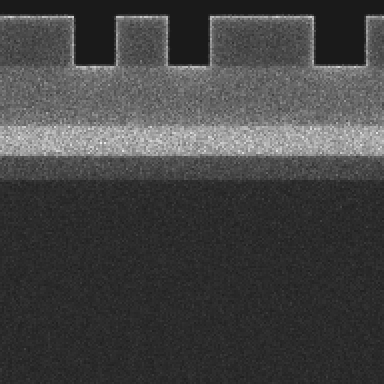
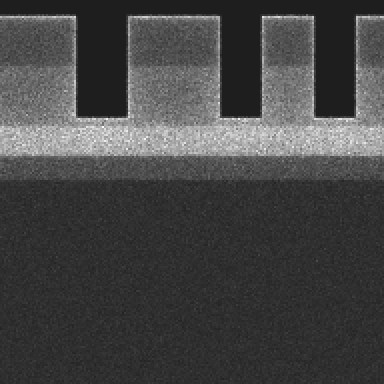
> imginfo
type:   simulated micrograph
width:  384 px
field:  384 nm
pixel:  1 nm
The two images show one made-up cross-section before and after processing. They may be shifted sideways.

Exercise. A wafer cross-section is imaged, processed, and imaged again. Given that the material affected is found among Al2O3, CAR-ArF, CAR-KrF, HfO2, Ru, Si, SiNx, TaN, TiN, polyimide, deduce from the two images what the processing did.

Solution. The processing removed Ru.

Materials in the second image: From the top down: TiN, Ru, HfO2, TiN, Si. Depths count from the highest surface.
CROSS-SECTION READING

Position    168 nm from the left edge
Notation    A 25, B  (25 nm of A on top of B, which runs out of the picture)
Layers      TiN 50, Ru 60, HfO2 30, TiN 24, Si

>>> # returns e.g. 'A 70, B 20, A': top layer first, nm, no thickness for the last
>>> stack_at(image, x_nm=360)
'TiN 50, Ru 60, HfO2 30, TiN 24, Si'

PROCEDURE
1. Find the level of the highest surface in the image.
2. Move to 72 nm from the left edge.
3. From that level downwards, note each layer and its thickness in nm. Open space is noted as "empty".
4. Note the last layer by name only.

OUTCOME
TiN 50, Ru 60, HfO2 30, TiN 24, Si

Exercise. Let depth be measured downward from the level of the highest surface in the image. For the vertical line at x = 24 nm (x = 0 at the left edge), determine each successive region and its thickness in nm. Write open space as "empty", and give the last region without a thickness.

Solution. TiN 50, Ru 60, HfO2 30, TiN 24, Si